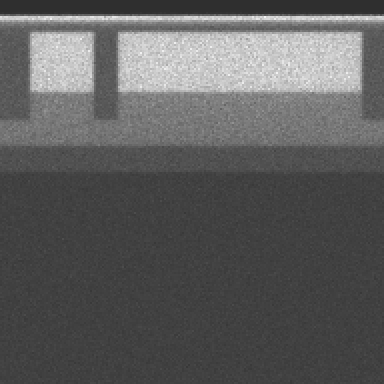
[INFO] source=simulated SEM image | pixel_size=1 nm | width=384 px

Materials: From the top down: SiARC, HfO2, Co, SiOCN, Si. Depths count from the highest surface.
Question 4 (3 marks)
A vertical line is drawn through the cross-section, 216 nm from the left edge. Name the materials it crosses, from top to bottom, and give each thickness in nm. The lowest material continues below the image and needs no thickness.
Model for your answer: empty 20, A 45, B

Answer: SiARC 16, HfO2 60, Co 54, SiOCN 26, Si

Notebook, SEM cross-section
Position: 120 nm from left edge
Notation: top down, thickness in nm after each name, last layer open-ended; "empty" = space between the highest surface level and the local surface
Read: SiARC 16, HfO2 60, Co 54, SiOCN 26, Si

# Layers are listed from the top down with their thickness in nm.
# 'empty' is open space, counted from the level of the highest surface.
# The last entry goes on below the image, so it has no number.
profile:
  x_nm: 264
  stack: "SiARC 16, HfO2 60, Co 54, SiOCN 26, Si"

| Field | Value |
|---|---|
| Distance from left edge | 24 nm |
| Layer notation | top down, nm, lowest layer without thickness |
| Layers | SiARC 104, Co 26, SiOCN 26, Si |